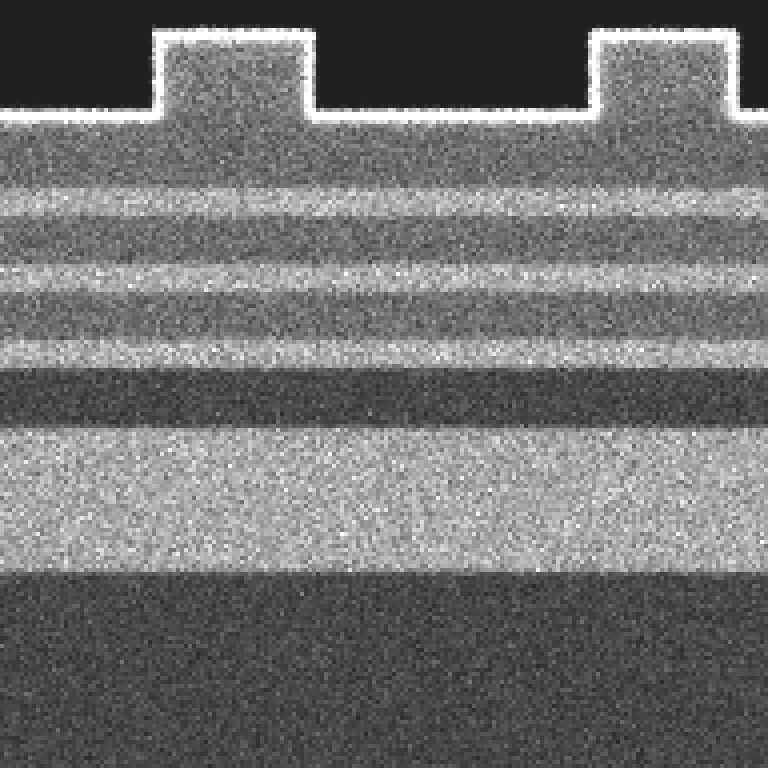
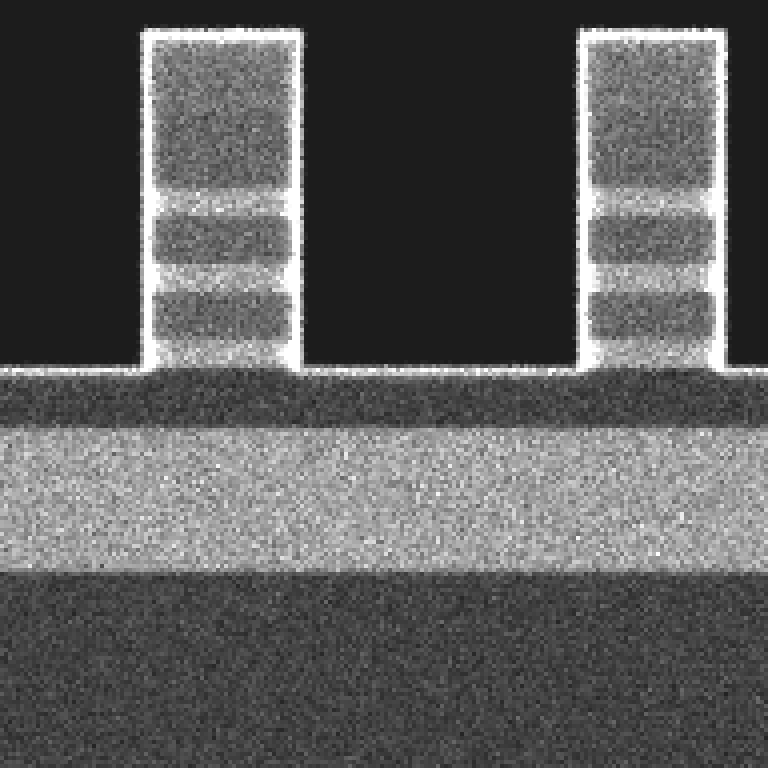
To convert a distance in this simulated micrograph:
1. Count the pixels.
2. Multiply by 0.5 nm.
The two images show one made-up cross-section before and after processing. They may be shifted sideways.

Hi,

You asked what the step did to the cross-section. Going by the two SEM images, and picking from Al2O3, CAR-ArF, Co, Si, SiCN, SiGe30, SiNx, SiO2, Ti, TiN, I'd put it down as Al2O3 and SiNx, removed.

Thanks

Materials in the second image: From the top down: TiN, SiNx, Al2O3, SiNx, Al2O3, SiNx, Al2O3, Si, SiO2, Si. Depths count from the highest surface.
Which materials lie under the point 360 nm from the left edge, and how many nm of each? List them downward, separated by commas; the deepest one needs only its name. TiN 40, SiNx 38, Al2O3 14, SiNx 24, Al2O3 14, SiNx 24, Al2O3 14, Si 30, SiO2 72, Si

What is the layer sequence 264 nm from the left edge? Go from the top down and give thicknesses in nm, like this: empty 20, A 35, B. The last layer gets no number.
empty 168, Si 30, SiO2 72, Si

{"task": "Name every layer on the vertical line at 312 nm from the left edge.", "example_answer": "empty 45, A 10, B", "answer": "TiN 40, SiNx 38, Al2O3 14, SiNx 24, Al2O3 14, SiNx 24, Al2O3 14, Si 30, SiO2 72, Si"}